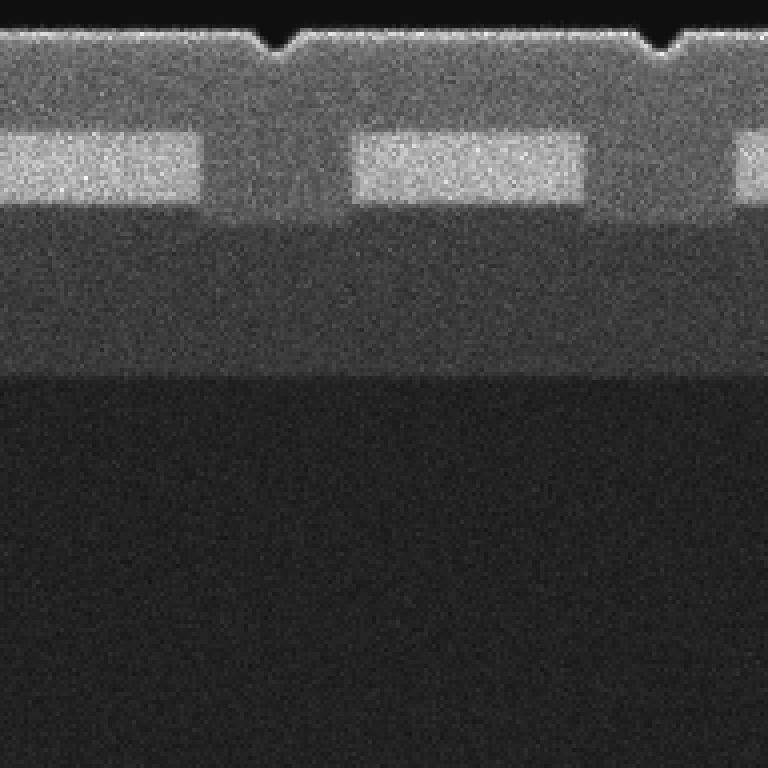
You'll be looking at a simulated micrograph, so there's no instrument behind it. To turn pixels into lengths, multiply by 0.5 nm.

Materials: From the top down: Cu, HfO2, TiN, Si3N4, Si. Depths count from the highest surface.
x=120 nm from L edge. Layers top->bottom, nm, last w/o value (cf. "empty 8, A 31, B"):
Cu 96, TiN 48, Si3N4 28, Si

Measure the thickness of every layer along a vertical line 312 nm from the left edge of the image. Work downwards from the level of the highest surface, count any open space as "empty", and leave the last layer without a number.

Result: Cu 96, TiN 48, Si3N4 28, Si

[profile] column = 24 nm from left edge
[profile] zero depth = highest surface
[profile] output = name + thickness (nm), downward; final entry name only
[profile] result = Cu 50, HfO2 36, TiN 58, Si3N4 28, Si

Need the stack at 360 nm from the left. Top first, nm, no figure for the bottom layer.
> Cu 96, TiN 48, Si3N4 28, Si